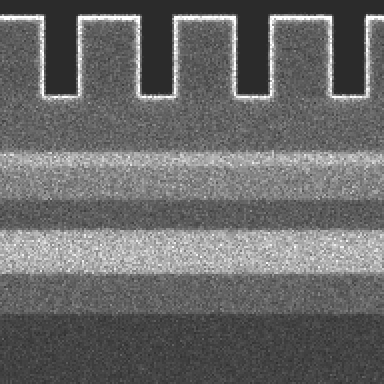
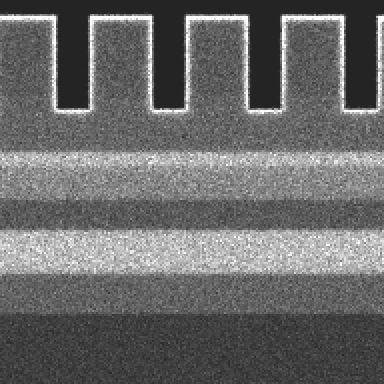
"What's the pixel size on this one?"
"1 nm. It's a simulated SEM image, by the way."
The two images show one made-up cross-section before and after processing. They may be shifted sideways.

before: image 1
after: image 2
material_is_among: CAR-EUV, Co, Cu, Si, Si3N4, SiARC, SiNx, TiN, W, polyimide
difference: TiN, removed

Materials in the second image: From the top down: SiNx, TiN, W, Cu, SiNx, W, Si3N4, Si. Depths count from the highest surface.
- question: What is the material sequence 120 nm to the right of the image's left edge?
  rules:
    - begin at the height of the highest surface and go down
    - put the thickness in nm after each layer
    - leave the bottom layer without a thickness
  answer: SiNx 80, TiN 56, W 14, Cu 34, SiNx 30, W 44, Si3N4 40, Si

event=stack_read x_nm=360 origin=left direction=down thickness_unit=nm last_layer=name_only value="empty 94, TiN 42, W 14, Cu 34, SiNx 30, W 44, Si3N4 40, Si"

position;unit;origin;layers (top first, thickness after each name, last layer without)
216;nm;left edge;SiNx 80, TiN 56, W 14, Cu 34, SiNx 30, W 44, Si3N4 40, Si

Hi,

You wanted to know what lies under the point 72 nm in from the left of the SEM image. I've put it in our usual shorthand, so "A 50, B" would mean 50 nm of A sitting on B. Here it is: empty 94, TiN 42, W 14, Cu 34, SiNx 30, W 44, Si3N4 40, Si